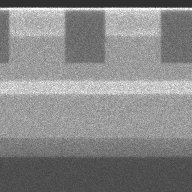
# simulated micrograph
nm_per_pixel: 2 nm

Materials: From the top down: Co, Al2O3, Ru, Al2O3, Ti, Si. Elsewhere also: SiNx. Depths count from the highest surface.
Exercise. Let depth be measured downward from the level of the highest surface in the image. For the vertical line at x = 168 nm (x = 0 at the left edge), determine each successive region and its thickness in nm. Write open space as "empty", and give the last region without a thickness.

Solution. SiNx 110, Al2O3 36, Ru 26, Al2O3 88, Ti 38, Si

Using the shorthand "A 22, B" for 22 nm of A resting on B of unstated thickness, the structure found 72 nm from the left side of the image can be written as Co 56, Al2O3 90, Ru 26, Al2O3 88, Ti 38, Si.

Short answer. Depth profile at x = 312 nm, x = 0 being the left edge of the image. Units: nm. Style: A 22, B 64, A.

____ Co 56, Al2O3 90, Ru 26, Al2O3 88, Ti 38, Si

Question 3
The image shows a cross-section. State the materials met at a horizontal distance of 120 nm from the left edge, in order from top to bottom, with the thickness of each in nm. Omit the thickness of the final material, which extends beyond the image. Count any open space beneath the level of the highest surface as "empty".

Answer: Co 56, Al2O3 90, Ru 26, Al2O3 88, Ti 38, Si